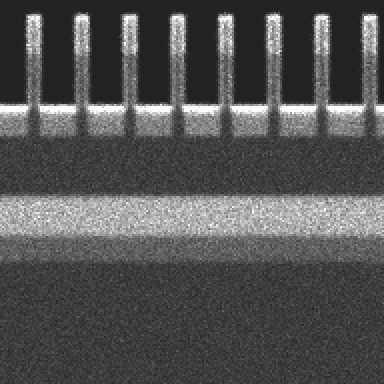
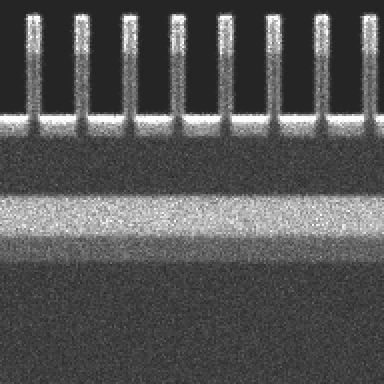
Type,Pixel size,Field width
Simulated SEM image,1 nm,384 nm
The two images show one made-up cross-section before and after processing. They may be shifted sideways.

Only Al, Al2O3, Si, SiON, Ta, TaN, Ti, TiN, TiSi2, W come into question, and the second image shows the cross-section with Al2O3 removed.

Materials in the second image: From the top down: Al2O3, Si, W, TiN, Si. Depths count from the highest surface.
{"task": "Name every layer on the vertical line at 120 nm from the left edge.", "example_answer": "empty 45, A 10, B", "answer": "empty 100, Al2O3 20, Si 60, W 40, TiN 26, Si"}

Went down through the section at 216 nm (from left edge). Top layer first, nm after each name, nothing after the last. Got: empty 100, Al2O3 20, Si 60, W 40, TiN 26, Si